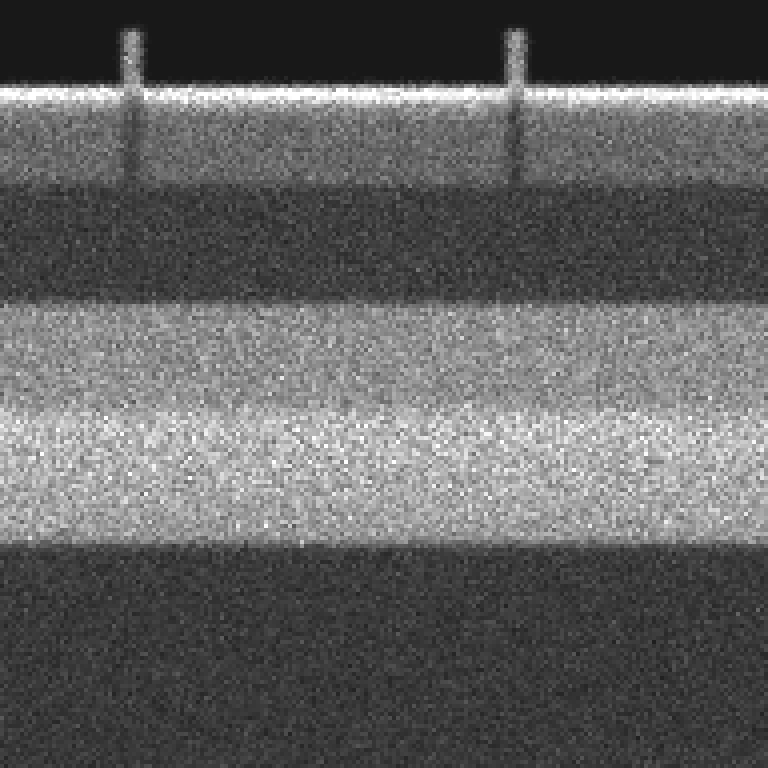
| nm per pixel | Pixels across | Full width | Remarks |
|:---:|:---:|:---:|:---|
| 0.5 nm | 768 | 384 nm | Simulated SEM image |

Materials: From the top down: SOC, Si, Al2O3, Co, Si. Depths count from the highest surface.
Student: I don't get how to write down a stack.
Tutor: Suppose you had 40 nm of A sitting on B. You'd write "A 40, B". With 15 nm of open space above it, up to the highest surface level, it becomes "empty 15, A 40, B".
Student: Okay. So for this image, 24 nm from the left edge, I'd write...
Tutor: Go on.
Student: empty 28, SOC 48, Si 60, Al2O3 54, Co 66, Si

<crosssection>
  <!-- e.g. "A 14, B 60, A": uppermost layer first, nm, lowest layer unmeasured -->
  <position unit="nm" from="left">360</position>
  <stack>empty 28, SOC 48, Si 60, Al2O3 54, Co 66, Si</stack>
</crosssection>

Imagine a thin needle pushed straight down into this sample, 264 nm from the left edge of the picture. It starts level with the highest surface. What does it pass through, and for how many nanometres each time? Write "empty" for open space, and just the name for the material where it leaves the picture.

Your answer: empty 28, SOC 48, Si 60, Al2O3 54, Co 66, Si